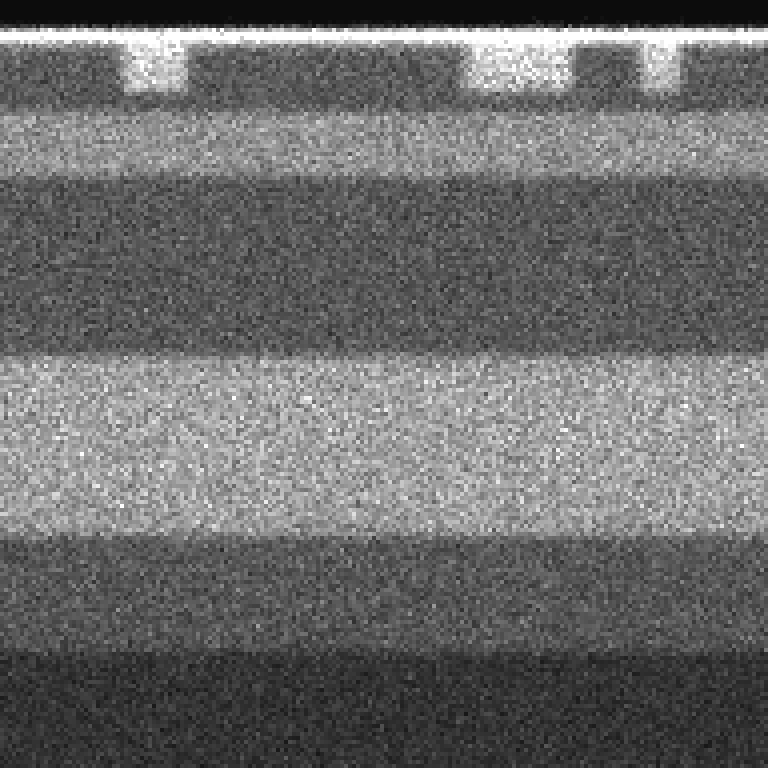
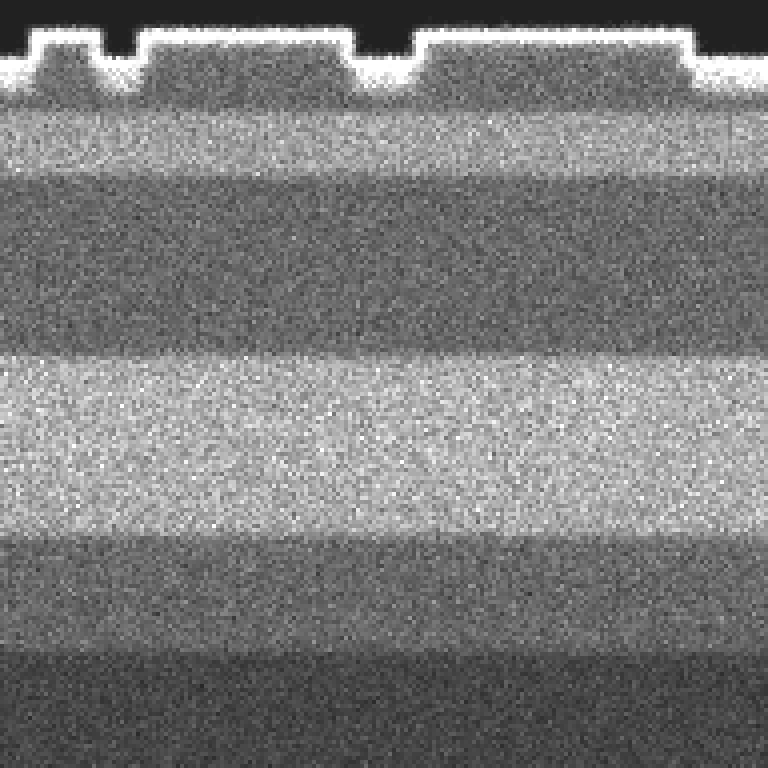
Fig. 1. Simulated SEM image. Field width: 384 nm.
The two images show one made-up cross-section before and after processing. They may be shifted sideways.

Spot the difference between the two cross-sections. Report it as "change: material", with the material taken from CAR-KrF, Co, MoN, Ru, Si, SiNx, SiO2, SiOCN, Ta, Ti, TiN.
removed: Ru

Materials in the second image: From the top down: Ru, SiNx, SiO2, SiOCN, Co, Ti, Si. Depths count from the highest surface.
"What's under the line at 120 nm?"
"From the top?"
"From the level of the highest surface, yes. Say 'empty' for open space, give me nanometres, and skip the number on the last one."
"SiNx 40, SiO2 32, SiOCN 90, Co 90, Ti 58, Si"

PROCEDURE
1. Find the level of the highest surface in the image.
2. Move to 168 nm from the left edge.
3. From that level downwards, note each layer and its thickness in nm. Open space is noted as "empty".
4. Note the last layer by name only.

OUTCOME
SiNx 40, SiO2 32, SiOCN 90, Co 90, Ti 58, Si